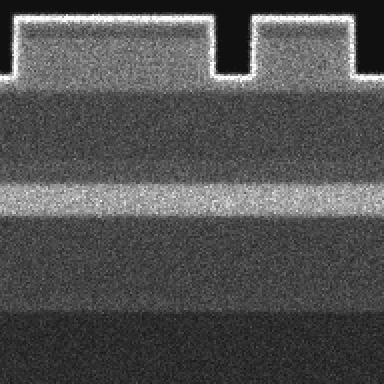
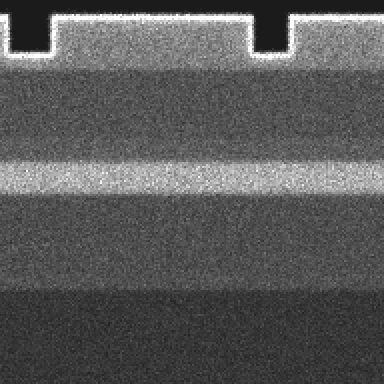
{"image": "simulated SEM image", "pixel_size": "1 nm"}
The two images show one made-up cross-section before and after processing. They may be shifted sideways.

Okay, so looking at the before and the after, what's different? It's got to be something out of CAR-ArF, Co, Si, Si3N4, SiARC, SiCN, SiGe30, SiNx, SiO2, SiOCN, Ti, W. SiARC, removed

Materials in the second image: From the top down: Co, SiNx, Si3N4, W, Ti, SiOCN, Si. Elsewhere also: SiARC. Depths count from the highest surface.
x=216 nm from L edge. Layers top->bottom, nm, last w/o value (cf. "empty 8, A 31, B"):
Co 54, SiNx 68, Si3N4 24, W 32, Ti 80, SiOCN 16, Si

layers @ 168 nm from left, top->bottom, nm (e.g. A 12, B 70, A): Co 54, SiNx 68, Si3N4 24, W 32, Ti 80, SiOCN 16, Si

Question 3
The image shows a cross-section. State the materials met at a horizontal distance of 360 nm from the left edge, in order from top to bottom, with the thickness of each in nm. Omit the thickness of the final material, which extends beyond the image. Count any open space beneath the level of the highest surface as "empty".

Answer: Co 54, SiNx 68, Si3N4 24, W 32, Ti 80, SiOCN 16, Si